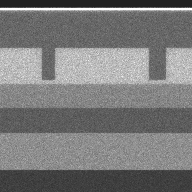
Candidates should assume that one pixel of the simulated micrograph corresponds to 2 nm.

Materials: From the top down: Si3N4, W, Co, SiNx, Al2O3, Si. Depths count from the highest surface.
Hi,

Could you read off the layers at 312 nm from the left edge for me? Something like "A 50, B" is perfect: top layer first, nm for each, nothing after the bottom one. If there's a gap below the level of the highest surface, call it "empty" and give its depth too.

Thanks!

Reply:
Si3N4 144, W 8, Co 48, SiNx 50, Al2O3 74, Si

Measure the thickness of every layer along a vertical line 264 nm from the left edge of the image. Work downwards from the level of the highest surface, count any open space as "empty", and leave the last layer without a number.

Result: Si3N4 80, W 72, Co 48, SiNx 50, Al2O3 74, Si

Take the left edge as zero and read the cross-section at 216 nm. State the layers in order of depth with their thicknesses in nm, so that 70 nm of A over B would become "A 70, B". Si3N4 80, W 72, Co 48, SiNx 50, Al2O3 74, Si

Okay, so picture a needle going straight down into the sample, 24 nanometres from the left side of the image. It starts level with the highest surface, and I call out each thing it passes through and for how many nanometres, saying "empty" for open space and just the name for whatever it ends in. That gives Si3N4 80, W 72, Co 48, SiNx 50, Al2O3 74, Si